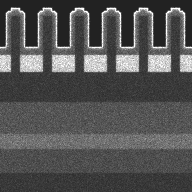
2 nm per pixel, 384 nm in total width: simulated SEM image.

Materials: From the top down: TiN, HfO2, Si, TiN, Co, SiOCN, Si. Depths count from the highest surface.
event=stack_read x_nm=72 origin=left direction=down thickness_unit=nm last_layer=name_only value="empty 78, TiN 16, HfO2 34, Si 60, TiN 64, Co 30, SiOCN 48, Si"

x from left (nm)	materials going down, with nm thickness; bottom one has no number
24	TiN 16, Si 172, TiN 64, Co 30, SiOCN 48, Si